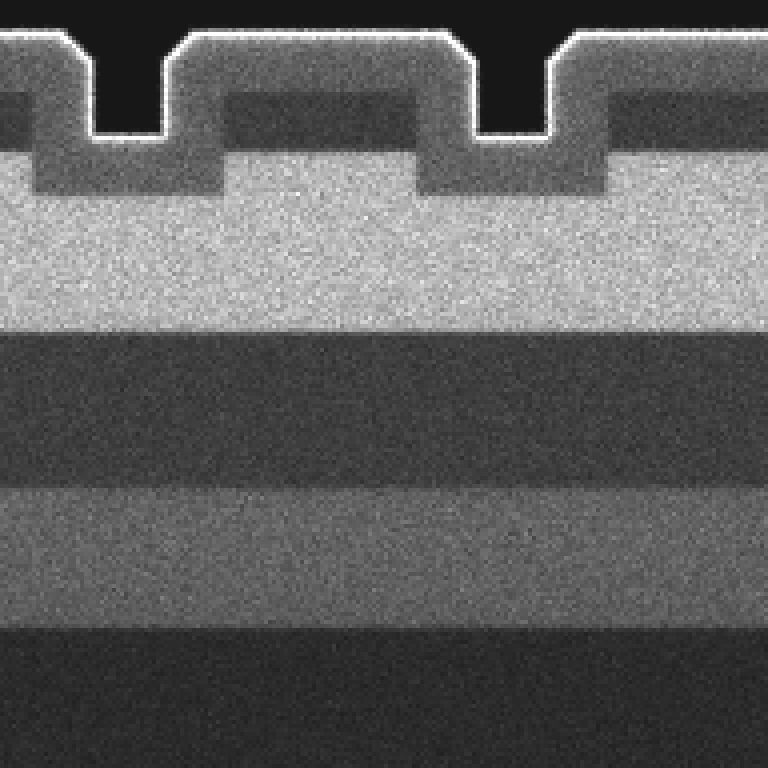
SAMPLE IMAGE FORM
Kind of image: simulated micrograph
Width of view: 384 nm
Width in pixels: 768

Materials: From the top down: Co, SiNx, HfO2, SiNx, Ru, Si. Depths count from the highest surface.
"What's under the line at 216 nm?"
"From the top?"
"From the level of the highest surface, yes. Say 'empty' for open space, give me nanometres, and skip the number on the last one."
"Co 82, HfO2 68, SiNx 78, Ru 70, Si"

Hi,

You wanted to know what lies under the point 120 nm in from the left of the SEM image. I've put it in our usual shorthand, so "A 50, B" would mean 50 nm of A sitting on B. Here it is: Co 30, SiNx 30, HfO2 90, SiNx 78, Ru 70, Si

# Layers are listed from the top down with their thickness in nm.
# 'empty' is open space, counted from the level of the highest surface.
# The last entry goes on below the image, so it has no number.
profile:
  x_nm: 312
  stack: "Co 30, SiNx 30, HfO2 90, SiNx 78, Ru 70, Si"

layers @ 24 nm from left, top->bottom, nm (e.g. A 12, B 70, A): Co 82, HfO2 68, SiNx 78, Ru 70, Si